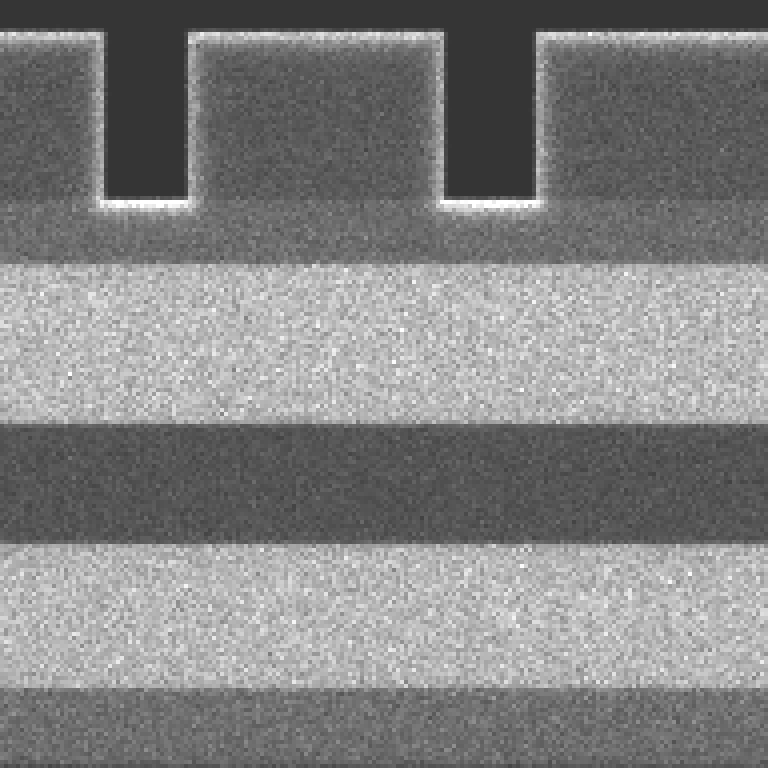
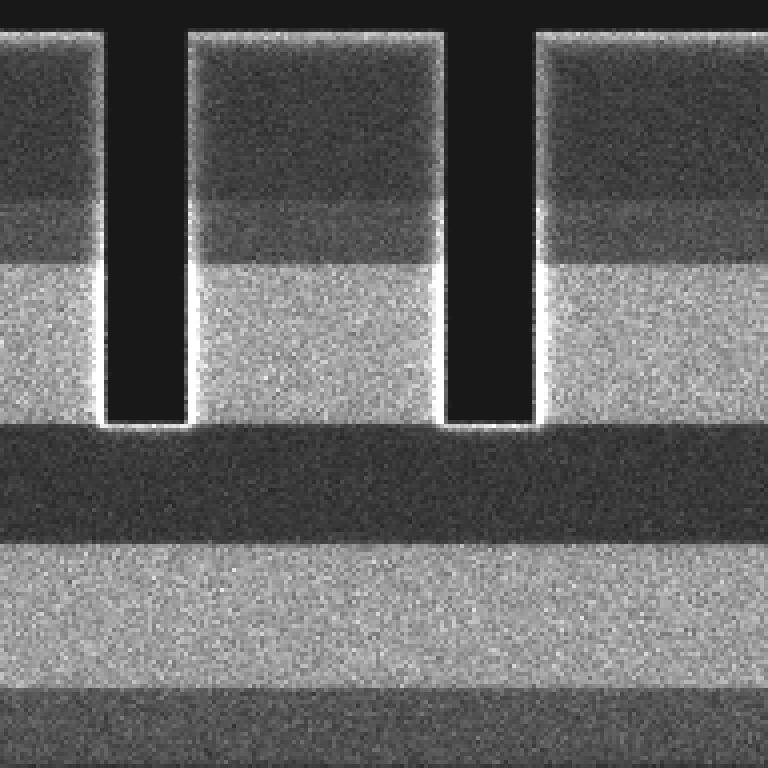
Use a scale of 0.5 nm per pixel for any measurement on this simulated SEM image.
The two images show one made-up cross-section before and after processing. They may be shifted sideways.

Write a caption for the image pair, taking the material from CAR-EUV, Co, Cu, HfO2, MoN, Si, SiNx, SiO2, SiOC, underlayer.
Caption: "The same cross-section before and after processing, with HfO2 and SiO2 removed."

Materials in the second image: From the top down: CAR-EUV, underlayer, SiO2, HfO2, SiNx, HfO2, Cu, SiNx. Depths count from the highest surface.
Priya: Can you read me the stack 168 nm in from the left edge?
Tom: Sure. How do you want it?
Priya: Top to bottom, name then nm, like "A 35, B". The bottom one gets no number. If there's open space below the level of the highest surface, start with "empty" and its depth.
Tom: CAR-EUV 54, underlayer 30, SiO2 32, HfO2 80, SiNx 60, HfO2 72, Cu 38, SiNx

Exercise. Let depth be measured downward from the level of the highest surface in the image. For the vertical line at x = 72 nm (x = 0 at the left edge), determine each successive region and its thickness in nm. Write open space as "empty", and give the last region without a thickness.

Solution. empty 196, SiNx 60, HfO2 72, Cu 38, SiNx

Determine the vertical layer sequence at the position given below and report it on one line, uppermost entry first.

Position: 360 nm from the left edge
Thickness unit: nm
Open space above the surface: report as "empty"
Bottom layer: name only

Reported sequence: CAR-EUV 54, underlayer 30, SiO2 32, HfO2 80, SiNx 60, HfO2 72, Cu 38, SiNx